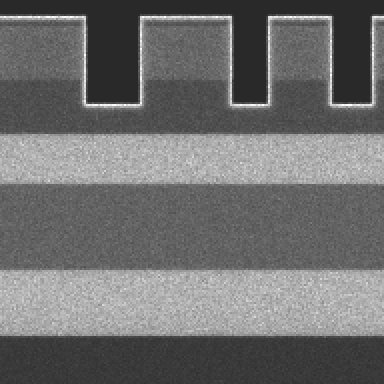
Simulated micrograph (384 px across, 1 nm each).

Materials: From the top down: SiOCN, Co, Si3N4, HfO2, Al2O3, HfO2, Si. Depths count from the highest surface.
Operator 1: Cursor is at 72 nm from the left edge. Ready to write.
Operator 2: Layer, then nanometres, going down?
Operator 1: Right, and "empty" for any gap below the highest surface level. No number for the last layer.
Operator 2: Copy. SiOCN 10, Co 54, Si3N4 54, HfO2 50, Al2O3 86, HfO2 66, Si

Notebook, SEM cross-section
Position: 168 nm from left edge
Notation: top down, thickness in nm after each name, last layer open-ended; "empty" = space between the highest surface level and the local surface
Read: SiOCN 10, Co 54, Si3N4 54, HfO2 50, Al2O3 86, HfO2 66, Si